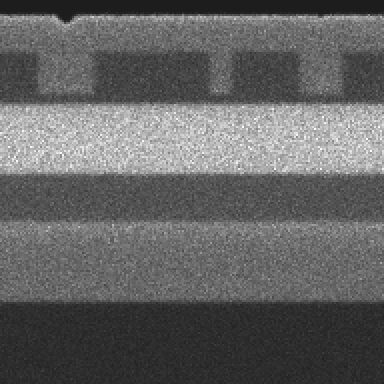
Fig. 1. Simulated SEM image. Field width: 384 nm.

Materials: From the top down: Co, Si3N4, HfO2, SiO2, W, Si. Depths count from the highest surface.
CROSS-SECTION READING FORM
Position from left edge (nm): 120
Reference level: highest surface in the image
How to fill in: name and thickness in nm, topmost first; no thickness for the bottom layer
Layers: Co 36, Si3N4 52, HfO2 70, SiO2 48, W 80, Si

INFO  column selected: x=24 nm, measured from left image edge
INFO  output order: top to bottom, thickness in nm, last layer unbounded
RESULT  Co 36, Si3N4 52, HfO2 70, SiO2 48, W 80, Si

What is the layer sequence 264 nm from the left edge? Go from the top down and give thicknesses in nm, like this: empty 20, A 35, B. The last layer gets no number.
Co 36, Si3N4 52, HfO2 70, SiO2 48, W 80, Si